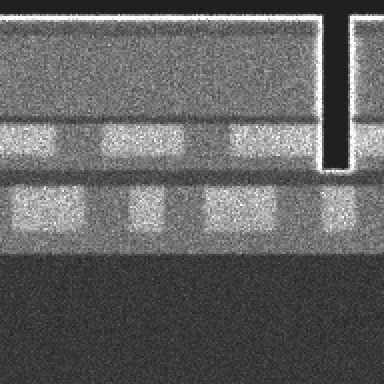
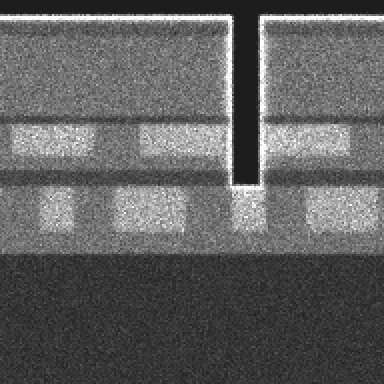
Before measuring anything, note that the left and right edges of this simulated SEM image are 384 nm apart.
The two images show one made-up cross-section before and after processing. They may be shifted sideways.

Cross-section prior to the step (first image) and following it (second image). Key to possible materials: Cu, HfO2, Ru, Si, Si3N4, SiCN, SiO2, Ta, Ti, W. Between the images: SiCN was removed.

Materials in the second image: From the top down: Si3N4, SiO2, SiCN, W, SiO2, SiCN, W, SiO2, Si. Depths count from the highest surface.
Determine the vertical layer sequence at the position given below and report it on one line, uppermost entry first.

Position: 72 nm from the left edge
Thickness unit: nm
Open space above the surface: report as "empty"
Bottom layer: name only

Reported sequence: Si3N4 20, SiO2 80, SiCN 8, W 32, SiO2 14, SiCN 16, W 46, SiO2 22, Si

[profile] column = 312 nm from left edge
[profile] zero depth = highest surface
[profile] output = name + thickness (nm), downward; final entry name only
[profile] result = Si3N4 20, SiO2 80, SiCN 8, W 32, SiO2 14, SiCN 16, W 46, SiO2 22, Si